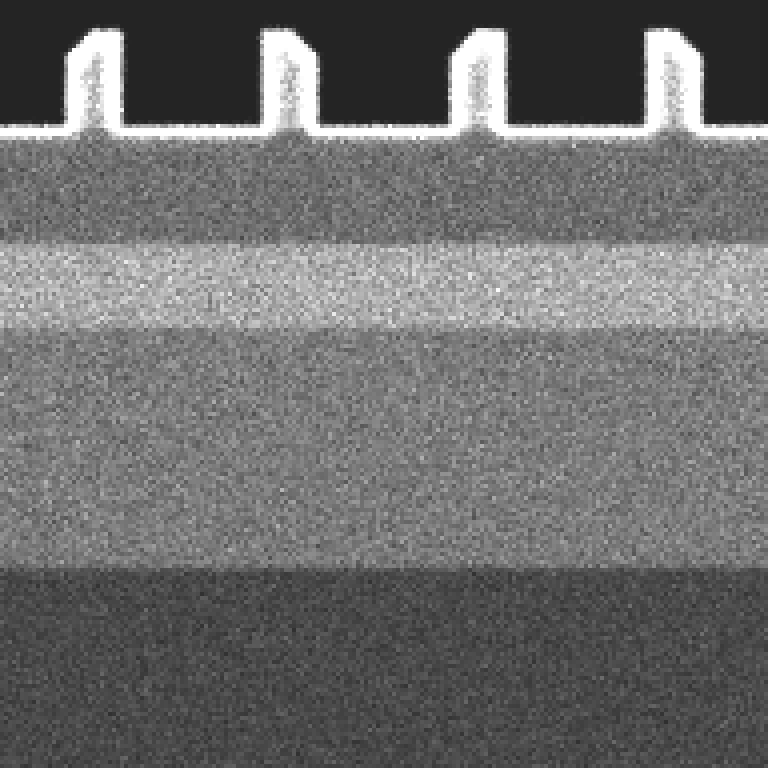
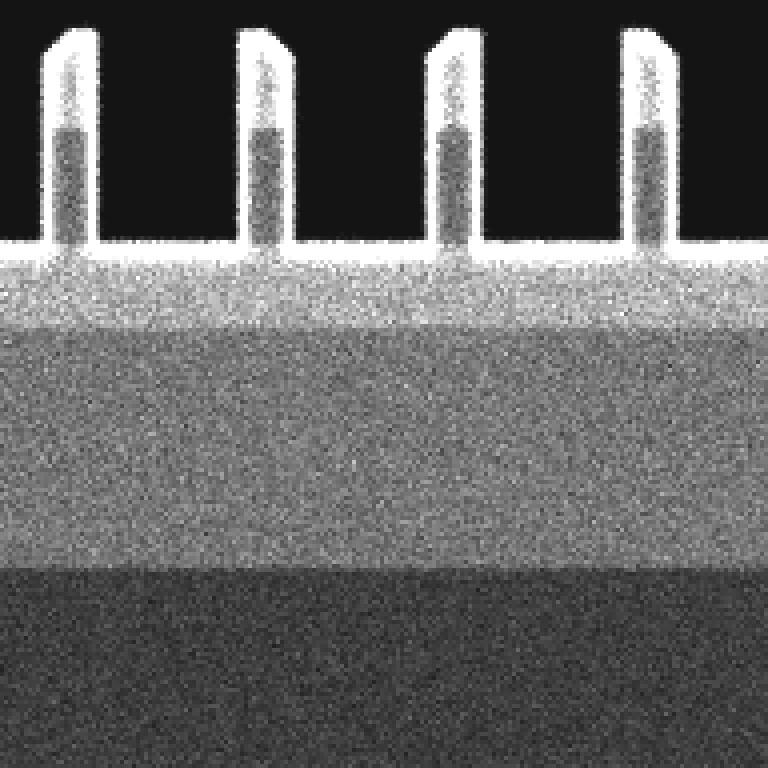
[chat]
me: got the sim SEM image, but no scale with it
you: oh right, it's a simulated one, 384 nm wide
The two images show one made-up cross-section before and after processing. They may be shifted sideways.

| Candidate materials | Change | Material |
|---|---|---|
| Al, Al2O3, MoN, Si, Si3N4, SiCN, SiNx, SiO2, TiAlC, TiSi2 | removed | SiNx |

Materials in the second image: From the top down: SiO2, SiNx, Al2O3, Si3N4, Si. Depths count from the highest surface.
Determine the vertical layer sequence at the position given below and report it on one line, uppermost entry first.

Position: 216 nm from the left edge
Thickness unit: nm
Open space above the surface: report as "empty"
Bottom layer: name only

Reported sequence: empty 10, SiO2 38, SiNx 58, Al2O3 42, Si3N4 120, Si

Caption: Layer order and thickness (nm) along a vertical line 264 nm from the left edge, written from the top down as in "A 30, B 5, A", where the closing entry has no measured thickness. empty 106, Al2O3 42, Si3N4 120, Si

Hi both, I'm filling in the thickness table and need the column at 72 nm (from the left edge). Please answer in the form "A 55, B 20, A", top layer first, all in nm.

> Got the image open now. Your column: empty 106, Al2O3 42, Si3N4 120, Si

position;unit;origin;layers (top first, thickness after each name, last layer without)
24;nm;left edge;empty 10, SiO2 38, SiNx 58, Al2O3 42, Si3N4 120, Si